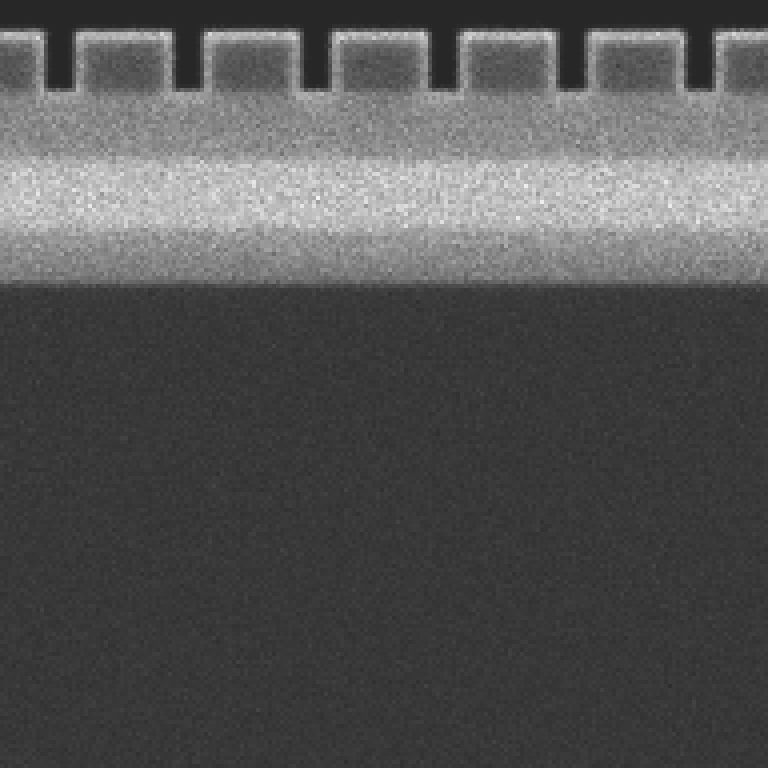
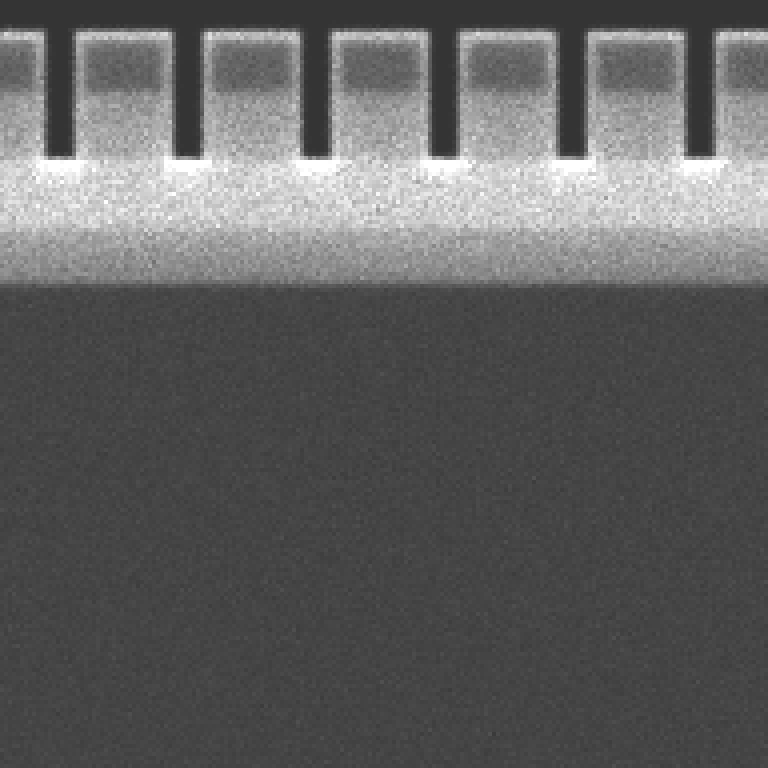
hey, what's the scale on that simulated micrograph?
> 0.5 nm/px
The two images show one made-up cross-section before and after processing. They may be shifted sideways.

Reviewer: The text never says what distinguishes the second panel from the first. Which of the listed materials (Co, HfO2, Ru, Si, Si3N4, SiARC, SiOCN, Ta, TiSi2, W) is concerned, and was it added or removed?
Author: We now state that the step removed Ru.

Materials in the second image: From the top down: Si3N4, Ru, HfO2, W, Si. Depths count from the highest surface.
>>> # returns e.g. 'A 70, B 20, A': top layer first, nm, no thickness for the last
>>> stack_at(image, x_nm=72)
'Si3N4 30, Ru 34, HfO2 34, W 28, Si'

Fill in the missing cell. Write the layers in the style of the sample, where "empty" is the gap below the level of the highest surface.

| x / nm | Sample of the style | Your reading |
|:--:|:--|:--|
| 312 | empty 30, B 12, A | Si3N4 30, Ru 34, HfO2 34, W 28, Si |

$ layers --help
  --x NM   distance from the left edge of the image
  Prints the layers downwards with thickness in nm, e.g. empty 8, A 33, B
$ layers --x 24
empty 64, HfO2 34, W 28, Si